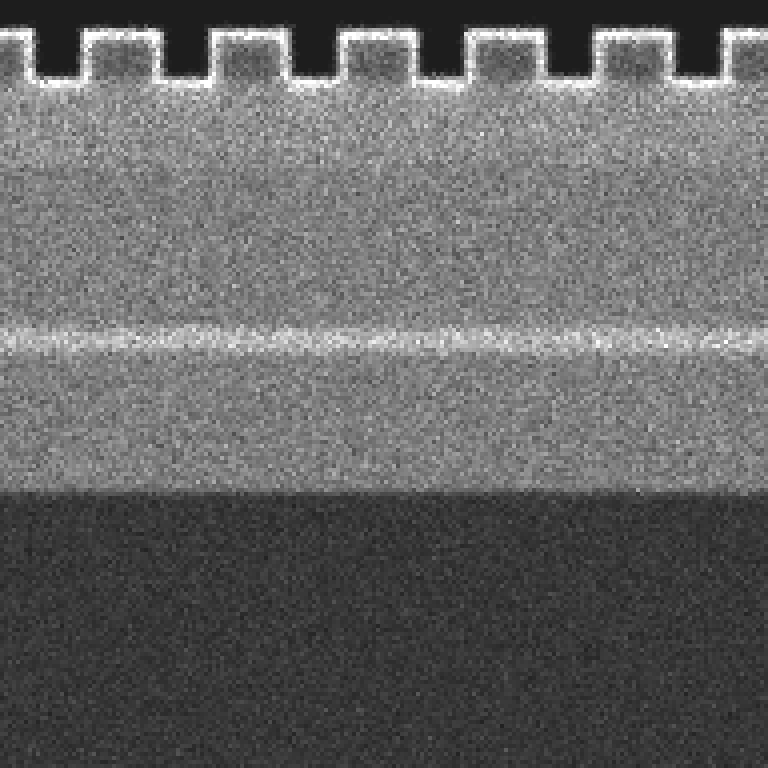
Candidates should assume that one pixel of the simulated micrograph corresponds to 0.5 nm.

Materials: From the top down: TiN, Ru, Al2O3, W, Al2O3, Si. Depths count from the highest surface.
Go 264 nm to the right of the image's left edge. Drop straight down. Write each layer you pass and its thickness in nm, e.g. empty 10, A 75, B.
TiN 24, Ru 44, Al2O3 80, W 12, Al2O3 70, Si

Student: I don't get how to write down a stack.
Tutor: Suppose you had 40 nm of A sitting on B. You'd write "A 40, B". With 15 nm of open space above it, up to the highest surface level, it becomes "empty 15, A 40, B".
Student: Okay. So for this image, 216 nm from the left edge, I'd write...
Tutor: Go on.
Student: empty 24, Ru 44, Al2O3 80, W 12, Al2O3 70, Si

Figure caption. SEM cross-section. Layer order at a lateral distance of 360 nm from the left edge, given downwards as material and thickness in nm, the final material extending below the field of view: empty 24, Ru 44, Al2O3 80, W 12, Al2O3 70, Si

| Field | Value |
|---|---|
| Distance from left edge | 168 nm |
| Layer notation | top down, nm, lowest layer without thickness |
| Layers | empty 24, Ru 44, Al2O3 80, W 12, Al2O3 70, Si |